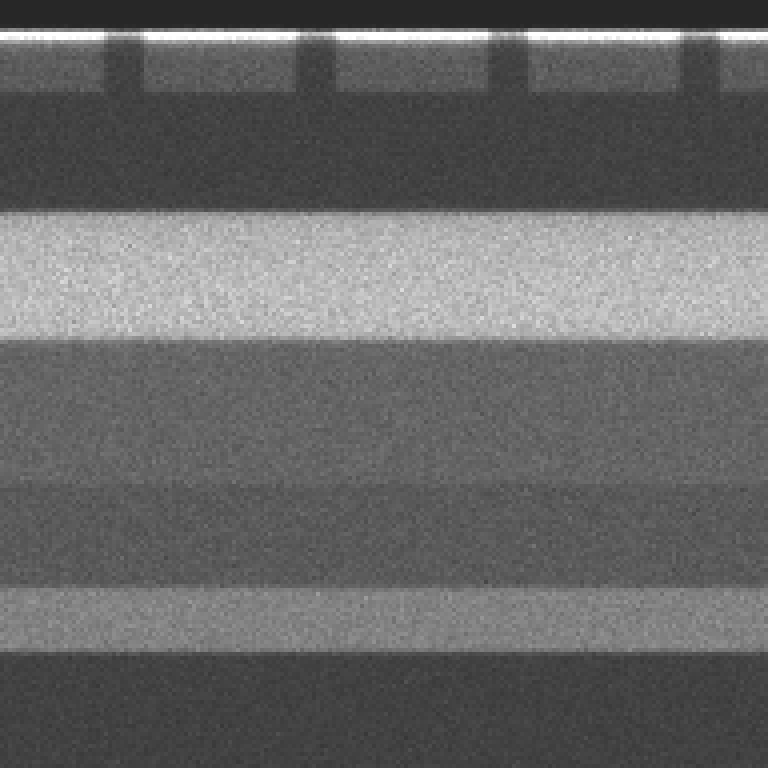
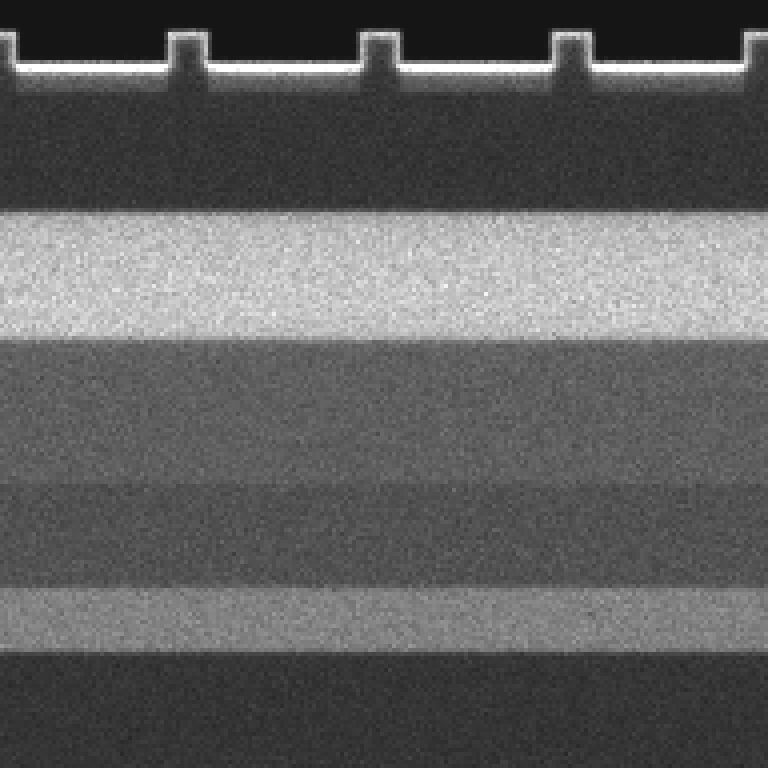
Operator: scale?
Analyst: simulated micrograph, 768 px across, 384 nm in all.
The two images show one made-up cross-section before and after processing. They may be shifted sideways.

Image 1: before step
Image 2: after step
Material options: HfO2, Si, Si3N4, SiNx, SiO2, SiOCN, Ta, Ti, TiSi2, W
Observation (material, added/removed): SiNx, removed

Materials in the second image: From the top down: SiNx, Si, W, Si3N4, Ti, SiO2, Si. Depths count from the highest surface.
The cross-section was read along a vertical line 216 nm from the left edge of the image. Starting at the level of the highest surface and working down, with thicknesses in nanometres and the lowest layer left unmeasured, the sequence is empty 16, SiNx 14, Si 60, W 64, Si3N4 72, Ti 52, SiO2 32, Si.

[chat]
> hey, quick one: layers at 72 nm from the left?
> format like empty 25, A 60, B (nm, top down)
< empty 16, SiNx 14, Si 60, W 64, Si3N4 72, Ti 52, SiO2 32, Si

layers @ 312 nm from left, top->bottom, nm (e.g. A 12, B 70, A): empty 16, SiNx 14, Si 60, W 64, Si3N4 72, Ti 52, SiO2 32, Si